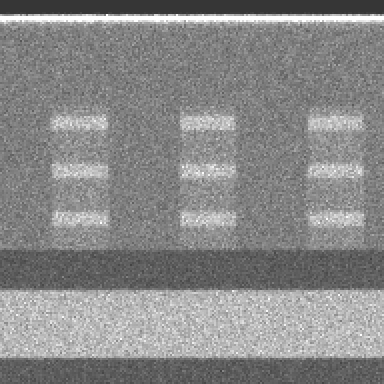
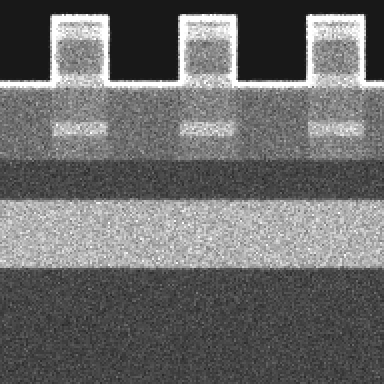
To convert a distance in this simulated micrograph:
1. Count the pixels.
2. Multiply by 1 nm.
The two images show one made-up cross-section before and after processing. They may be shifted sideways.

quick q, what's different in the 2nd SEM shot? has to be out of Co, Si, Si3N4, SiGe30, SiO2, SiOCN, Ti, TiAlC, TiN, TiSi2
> SiOCN removed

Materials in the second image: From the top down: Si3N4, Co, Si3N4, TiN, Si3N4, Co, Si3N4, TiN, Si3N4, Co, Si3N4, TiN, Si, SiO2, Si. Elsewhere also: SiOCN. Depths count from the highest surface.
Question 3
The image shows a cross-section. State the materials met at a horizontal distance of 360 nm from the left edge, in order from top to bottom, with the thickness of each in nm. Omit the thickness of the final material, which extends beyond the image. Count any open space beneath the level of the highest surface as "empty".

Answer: Si3N4 10, Co 14, Si3N4 10, TiN 14, Si3N4 10, Co 14, Si3N4 10, TiN 14, Si3N4 10, Co 14, Si3N4 10, TiN 14, Si 40, SiO2 68, Si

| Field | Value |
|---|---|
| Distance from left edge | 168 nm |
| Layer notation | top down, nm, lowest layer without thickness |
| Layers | empty 66, SiOCN 78, Si 40, SiO2 68, Si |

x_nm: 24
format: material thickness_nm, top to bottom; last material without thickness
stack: empty 66, SiOCN 78, Si 40, SiO2 68, Si